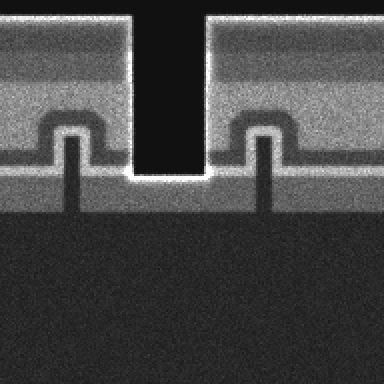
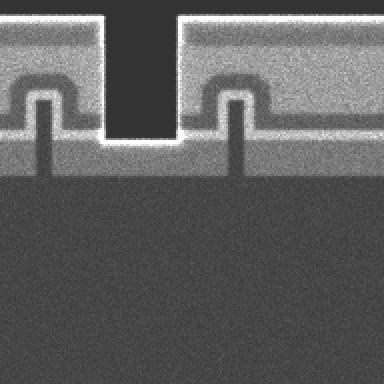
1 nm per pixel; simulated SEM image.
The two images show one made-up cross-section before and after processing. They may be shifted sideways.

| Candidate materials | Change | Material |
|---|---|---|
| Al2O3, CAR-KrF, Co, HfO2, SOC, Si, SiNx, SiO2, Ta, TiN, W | removed | SOC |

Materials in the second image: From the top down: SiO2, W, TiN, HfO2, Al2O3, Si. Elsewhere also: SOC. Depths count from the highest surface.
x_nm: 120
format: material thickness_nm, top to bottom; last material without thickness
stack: empty 124, Al2O3 36, Si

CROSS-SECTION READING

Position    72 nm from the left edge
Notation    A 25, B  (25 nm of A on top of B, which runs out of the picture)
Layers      SiO2 30, W 36, TiN 48, HfO2 10, Al2O3 36, Si